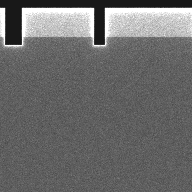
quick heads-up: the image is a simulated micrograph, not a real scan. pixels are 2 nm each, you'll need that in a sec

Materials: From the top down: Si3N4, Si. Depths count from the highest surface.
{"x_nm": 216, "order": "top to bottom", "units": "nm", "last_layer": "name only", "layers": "Si3N4 58, Si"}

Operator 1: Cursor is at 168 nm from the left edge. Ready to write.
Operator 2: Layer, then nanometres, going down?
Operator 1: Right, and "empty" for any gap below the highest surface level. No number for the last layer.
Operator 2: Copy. Si3N4 58, Si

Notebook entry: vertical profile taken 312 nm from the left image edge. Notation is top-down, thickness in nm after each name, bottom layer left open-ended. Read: Si3N4 58, Si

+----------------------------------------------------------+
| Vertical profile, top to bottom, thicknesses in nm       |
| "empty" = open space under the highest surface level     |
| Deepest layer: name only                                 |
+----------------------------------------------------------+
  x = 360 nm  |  Si3N4 58, Si